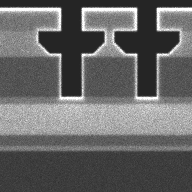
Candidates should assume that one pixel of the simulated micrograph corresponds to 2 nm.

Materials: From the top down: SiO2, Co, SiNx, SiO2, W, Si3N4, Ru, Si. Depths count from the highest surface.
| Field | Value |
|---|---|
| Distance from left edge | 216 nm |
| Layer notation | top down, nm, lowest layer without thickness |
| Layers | SiO2 46, Co 52, SiNx 80, SiO2 14, W 62, Si3N4 22, Ru 10, Si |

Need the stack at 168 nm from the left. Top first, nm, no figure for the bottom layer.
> SiO2 46, empty 46, Co 6, SiNx 80, SiO2 14, W 62, Si3N4 22, Ru 10, Si